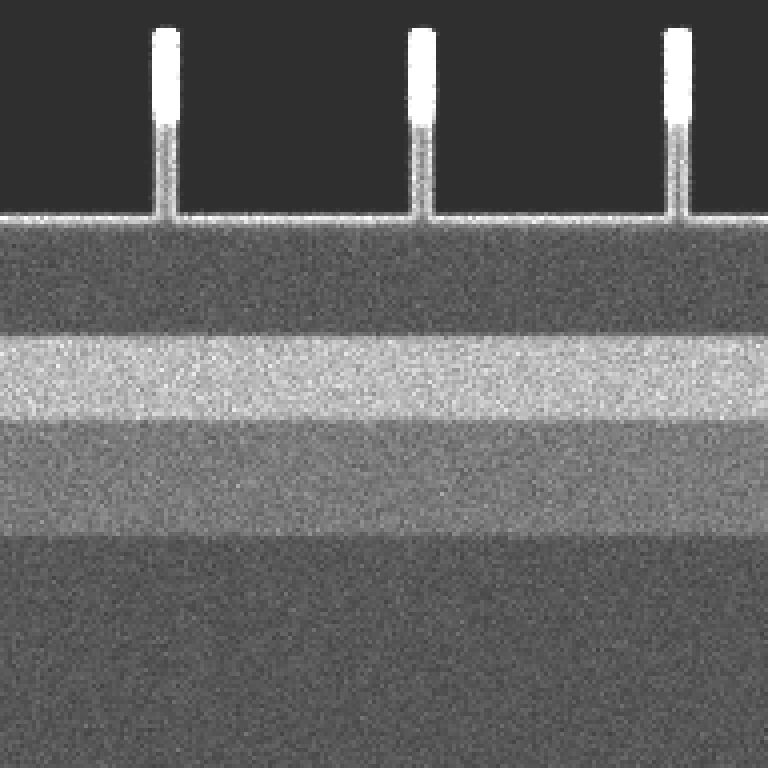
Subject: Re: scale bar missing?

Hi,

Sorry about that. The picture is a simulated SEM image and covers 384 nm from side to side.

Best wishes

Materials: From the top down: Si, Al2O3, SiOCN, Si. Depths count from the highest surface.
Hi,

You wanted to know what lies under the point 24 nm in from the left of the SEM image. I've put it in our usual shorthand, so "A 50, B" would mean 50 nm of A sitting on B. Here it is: empty 92, Si 60, Al2O3 42, SiOCN 58, Si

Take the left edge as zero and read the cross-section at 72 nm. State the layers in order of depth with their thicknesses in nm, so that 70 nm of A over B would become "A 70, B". empty 92, Si 60, Al2O3 42, SiOCN 58, Si